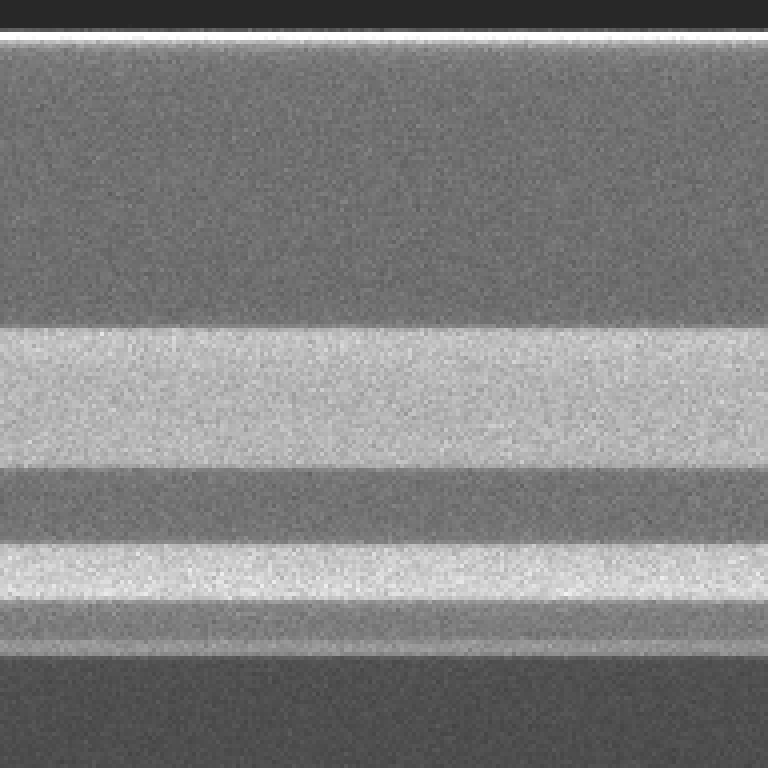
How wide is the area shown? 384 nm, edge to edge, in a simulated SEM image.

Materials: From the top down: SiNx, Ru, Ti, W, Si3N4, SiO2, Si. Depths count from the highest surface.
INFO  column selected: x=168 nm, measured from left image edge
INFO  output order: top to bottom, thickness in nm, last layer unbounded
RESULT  SiNx 148, Ru 70, Ti 38, W 28, Si3N4 20, SiO2 8, Si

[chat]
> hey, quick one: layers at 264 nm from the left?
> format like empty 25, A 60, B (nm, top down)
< SiNx 148, Ru 70, Ti 38, W 28, Si3N4 20, SiO2 8, Si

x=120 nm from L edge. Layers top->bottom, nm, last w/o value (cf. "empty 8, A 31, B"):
SiNx 148, Ru 70, Ti 38, W 28, Si3N4 20, SiO2 8, Si